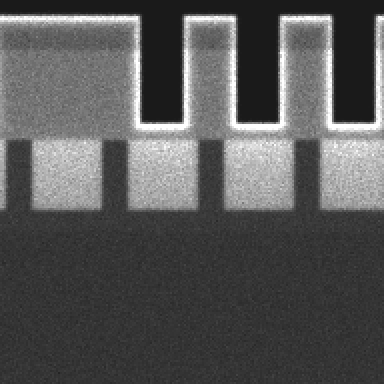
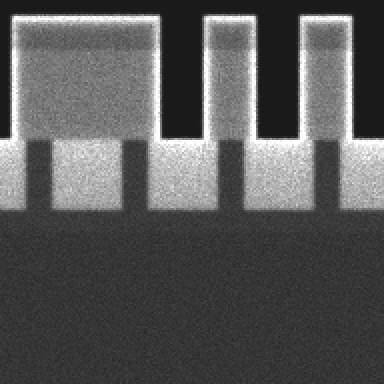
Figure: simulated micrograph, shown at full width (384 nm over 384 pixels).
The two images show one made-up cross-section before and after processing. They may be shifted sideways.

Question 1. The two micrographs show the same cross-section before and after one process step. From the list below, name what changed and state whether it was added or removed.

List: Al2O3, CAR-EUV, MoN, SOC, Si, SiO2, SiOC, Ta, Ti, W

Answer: Al2O3, removed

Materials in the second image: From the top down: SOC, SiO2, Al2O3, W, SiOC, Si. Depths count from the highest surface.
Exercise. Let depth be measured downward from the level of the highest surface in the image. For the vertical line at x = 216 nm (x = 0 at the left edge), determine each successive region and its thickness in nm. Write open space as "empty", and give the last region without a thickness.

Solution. SOC 34, SiO2 74, Al2O3 16, W 70, SiOC 22, Si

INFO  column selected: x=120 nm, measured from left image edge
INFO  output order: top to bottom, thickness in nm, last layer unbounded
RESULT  SOC 34, SiO2 74, Al2O3 16, W 70, SiOC 22, Si